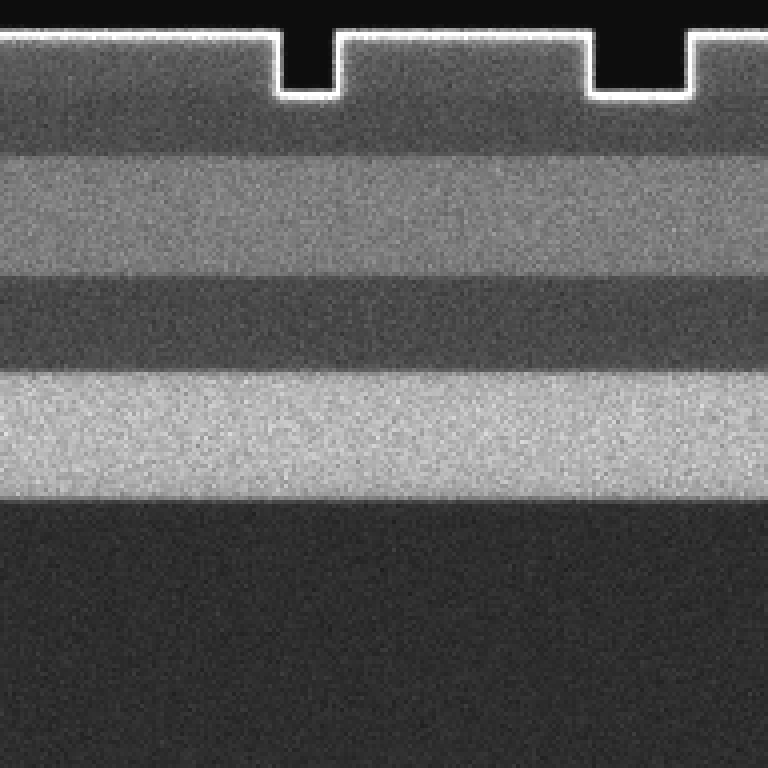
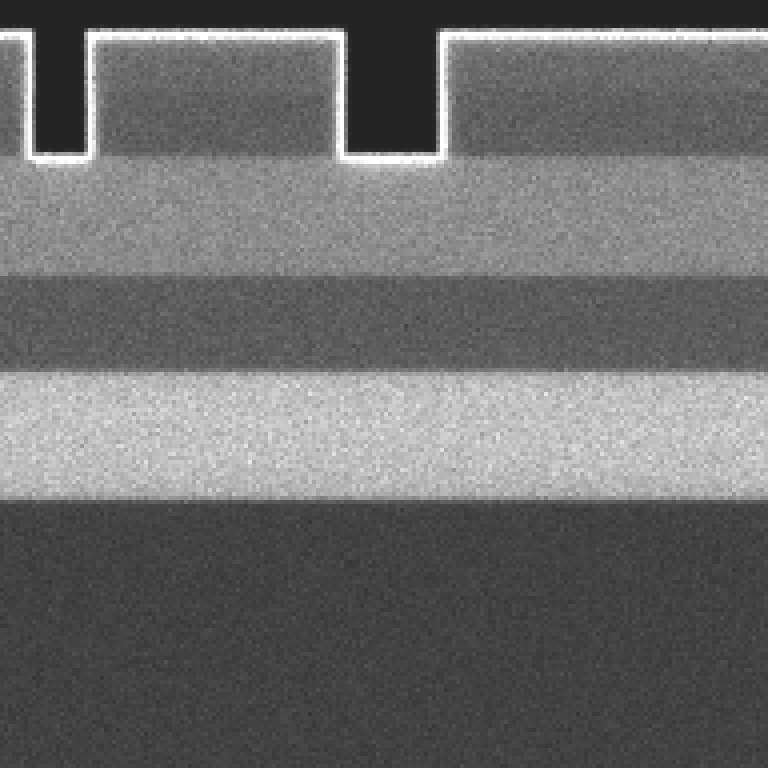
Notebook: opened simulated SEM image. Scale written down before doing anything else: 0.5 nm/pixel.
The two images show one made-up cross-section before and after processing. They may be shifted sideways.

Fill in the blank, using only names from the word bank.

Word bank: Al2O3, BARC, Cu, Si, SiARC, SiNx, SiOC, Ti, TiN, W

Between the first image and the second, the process removed SiNx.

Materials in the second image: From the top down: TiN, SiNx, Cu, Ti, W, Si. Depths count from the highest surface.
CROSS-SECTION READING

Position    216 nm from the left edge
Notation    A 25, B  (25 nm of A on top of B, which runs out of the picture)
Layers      empty 62, Cu 60, Ti 48, W 64, Si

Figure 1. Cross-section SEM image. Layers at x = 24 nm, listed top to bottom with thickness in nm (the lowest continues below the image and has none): empty 62, Cu 60, Ti 48, W 64, Si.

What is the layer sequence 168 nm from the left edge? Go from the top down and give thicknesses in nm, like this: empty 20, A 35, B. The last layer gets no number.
TiN 30, SiNx 32, Cu 60, Ti 48, W 64, Si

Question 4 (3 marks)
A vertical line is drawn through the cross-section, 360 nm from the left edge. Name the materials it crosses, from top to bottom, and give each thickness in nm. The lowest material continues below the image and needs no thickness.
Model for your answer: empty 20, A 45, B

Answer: TiN 30, SiNx 32, Cu 60, Ti 48, W 64, Si